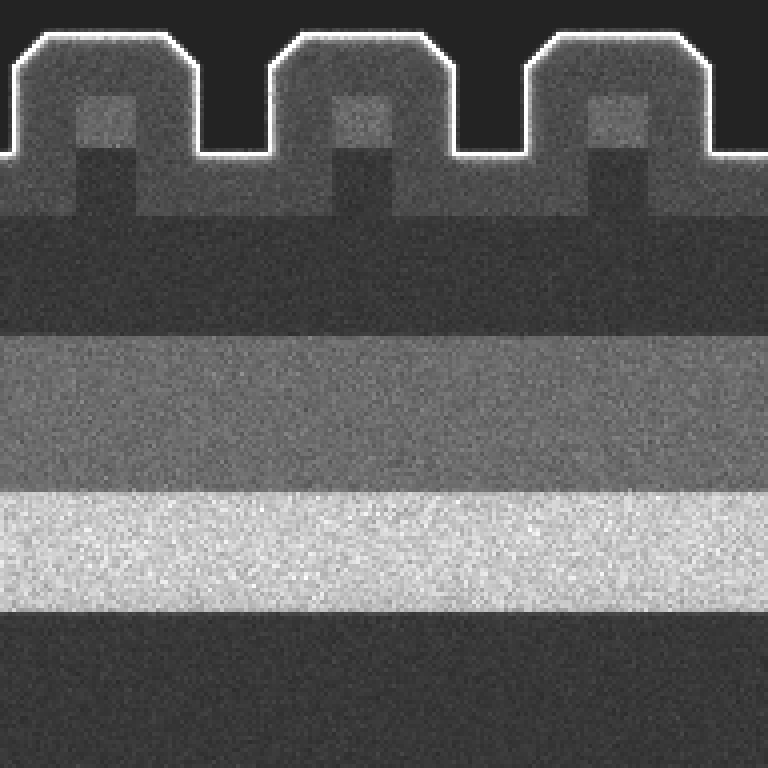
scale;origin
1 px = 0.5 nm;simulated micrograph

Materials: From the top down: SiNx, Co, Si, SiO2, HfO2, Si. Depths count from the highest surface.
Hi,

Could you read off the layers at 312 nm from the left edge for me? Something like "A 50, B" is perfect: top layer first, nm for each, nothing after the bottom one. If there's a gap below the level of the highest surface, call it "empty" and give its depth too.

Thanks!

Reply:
SiNx 32, Co 26, Si 94, SiO2 78, HfO2 60, Si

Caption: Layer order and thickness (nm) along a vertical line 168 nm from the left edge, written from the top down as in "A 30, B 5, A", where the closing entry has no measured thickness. SiNx 32, Co 26, Si 94, SiO2 78, HfO2 60, Si